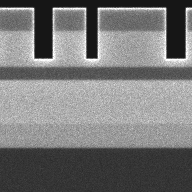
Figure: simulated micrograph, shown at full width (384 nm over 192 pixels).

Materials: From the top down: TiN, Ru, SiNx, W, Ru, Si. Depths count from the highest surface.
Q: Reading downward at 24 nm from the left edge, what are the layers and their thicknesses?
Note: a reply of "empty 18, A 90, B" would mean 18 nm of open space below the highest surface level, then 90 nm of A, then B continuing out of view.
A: TiN 46, Ru 72, SiNx 26, W 88, Ru 48, Si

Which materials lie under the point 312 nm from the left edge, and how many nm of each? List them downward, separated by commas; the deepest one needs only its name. TiN 46, Ru 72, SiNx 26, W 88, Ru 48, Si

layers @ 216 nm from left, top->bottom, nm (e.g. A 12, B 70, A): TiN 46, Ru 72, SiNx 26, W 88, Ru 48, Si